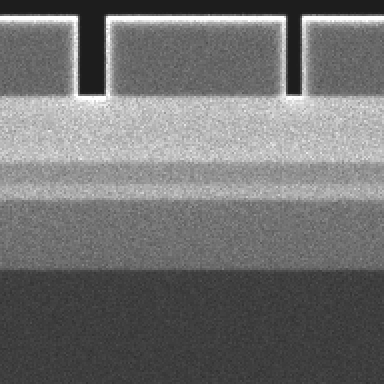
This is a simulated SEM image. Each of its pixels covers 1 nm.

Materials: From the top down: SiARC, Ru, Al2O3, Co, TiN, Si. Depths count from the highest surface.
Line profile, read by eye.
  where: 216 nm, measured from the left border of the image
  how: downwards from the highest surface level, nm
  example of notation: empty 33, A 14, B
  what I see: SiARC 80, Ru 66, Al2O3 22, Co 16, TiN 70, Si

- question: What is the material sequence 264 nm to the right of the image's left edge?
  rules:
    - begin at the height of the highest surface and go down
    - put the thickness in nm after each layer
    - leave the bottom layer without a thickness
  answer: SiARC 80, Ru 66, Al2O3 22, Co 16, TiN 70, Si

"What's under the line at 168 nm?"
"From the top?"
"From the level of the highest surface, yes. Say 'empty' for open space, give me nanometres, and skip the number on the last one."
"SiARC 80, Ru 66, Al2O3 22, Co 16, TiN 70, Si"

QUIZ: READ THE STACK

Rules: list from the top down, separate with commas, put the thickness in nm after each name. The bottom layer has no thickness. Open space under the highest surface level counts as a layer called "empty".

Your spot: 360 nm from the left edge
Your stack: SiARC 80, Ru 66, Al2O3 22, Co 16, TiN 70, Si